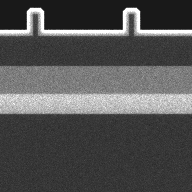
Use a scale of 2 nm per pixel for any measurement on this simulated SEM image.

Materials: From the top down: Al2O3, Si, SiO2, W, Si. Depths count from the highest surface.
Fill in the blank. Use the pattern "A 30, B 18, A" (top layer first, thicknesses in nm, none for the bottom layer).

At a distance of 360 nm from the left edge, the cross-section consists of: empty 44, Al2O3 12, Si 60, SiO2 56, W 40, Si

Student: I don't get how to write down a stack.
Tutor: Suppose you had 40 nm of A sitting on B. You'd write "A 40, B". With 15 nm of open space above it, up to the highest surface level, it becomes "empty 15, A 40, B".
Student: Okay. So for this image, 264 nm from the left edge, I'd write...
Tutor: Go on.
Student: Al2O3 12, Si 104, SiO2 56, W 40, Si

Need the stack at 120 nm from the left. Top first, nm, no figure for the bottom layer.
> empty 44, Al2O3 12, Si 60, SiO2 56, W 40, Si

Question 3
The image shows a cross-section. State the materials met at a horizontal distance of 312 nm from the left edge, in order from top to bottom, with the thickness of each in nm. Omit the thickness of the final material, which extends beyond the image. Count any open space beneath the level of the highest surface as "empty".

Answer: empty 44, Al2O3 12, Si 60, SiO2 56, W 40, Si